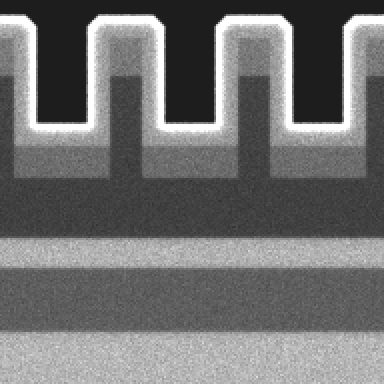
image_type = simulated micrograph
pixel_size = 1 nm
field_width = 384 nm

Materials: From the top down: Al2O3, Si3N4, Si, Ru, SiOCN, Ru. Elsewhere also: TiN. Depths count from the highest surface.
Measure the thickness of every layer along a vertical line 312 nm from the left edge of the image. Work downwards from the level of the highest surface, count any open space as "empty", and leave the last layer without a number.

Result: empty 108, Al2O3 22, Si3N4 32, Si 60, Ru 30, SiOCN 64, Ru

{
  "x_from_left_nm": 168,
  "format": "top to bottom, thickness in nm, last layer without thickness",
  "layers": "empty 108, Al2O3 22, Si3N4 32, Si 60, Ru 30, SiOCN 64, Ru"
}